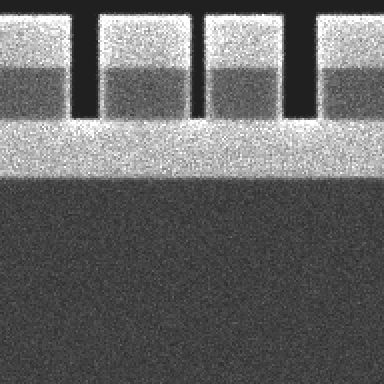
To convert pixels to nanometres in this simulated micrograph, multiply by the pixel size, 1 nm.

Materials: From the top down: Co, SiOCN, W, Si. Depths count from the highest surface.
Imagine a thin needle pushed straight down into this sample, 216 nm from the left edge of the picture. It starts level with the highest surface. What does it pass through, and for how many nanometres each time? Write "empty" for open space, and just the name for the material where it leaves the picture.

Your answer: Co 52, SiOCN 52, W 58, Si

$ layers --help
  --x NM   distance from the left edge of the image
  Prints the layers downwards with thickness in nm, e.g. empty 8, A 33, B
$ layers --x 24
Co 52, SiOCN 52, W 58, Si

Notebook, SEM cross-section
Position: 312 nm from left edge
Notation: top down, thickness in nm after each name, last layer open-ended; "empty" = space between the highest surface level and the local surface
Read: empty 104, W 58, Si